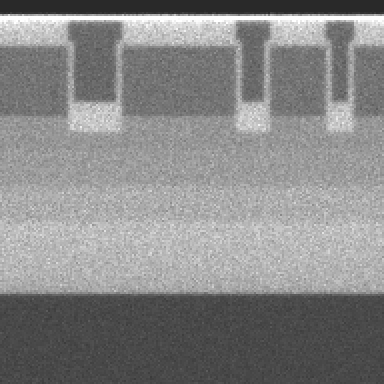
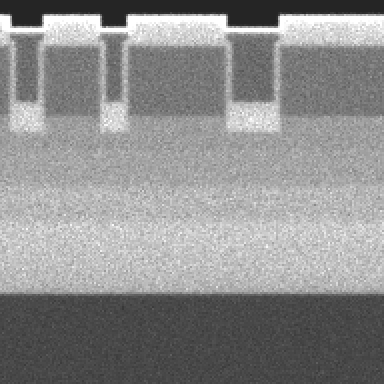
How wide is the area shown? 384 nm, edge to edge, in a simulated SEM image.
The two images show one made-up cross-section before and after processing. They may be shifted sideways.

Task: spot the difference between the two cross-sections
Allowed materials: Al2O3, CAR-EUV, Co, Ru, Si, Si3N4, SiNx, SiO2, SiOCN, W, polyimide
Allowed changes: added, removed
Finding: removed SiNx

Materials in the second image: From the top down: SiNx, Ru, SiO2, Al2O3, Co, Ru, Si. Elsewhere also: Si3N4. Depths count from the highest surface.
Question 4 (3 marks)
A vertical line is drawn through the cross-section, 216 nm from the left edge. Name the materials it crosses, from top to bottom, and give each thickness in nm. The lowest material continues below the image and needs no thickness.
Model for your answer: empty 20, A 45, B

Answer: Ru 30, Si3N4 70, SiO2 34, Al2O3 36, Co 36, Ru 72, Si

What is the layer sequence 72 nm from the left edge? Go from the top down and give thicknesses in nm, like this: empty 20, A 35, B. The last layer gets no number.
Ru 30, Si3N4 70, SiO2 34, Al2O3 36, Co 36, Ru 72, Si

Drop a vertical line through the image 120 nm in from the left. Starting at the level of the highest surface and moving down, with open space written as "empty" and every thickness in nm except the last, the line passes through empty 12, SiNx 74, Ru 30, SiO2 18, Al2O3 36, Co 36, Ru 72, Si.